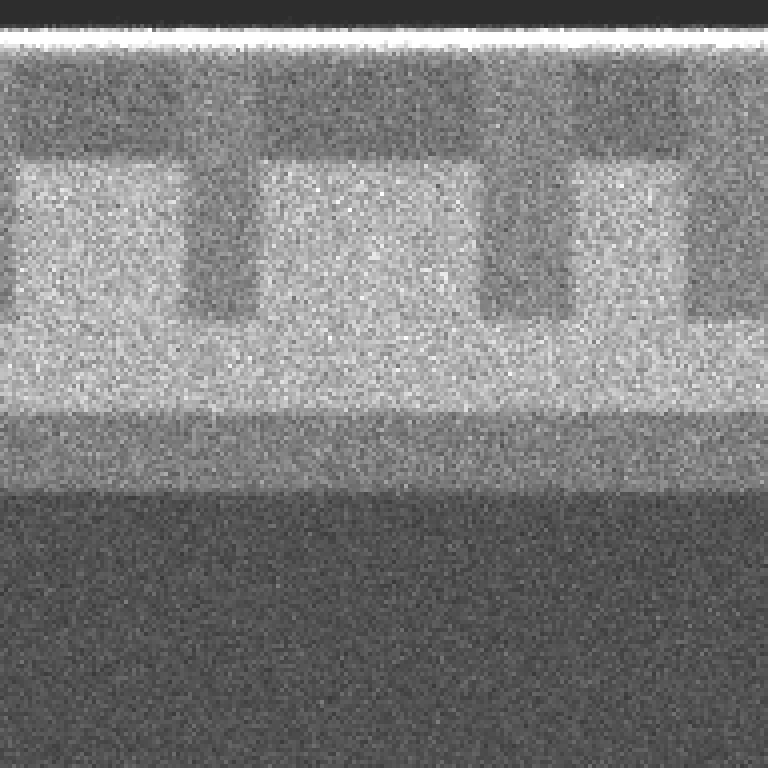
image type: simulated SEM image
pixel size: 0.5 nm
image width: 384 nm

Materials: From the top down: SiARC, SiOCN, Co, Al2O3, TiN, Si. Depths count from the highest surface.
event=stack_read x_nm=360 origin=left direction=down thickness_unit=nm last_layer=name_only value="SiARC 144, Al2O3 46, TiN 40, Si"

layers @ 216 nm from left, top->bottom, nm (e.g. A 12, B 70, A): SiARC 12, SiOCN 52, Co 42, Al2O3 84, TiN 40, Si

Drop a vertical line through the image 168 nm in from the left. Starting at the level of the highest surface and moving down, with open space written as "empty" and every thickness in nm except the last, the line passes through SiARC 12, SiOCN 52, Co 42, Al2O3 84, TiN 40, Si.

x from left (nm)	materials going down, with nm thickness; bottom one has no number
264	SiARC 144, Al2O3 46, TiN 40, Si